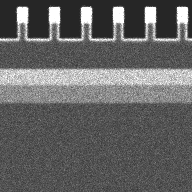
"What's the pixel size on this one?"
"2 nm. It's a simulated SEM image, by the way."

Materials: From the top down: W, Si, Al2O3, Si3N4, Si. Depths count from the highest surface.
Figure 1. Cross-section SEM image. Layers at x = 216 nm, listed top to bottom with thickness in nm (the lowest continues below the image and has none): empty 62, Si 60, Al2O3 32, Si3N4 36, Si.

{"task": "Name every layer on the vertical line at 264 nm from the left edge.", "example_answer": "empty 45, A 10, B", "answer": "empty 62, Si 60, Al2O3 32, Si3N4 36, Si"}